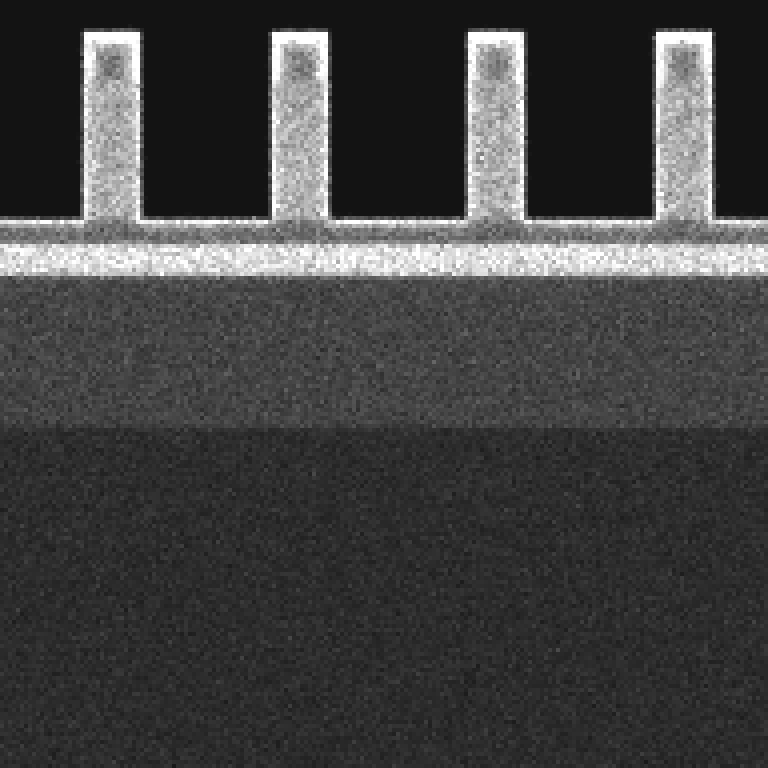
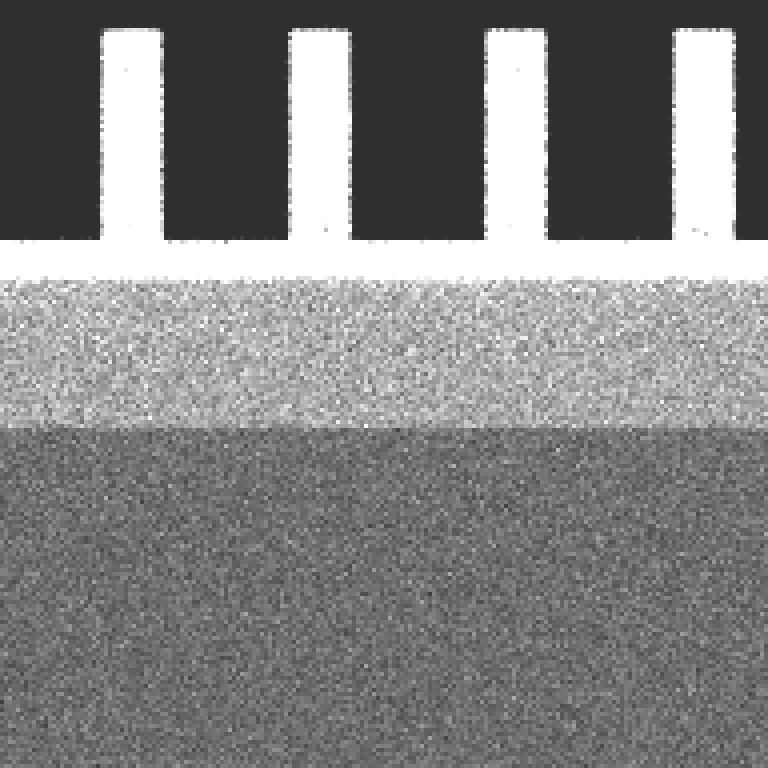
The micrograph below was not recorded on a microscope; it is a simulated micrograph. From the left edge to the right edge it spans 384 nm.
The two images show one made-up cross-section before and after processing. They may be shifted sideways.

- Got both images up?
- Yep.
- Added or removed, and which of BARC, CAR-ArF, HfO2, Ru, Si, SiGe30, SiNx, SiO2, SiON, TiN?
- removed, TiN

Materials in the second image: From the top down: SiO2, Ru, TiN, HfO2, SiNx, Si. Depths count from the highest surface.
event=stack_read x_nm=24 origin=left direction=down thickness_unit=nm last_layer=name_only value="empty 106, HfO2 16, SiNx 76, Si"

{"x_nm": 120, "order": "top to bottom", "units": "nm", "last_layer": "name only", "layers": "empty 106, HfO2 16, SiNx 76, Si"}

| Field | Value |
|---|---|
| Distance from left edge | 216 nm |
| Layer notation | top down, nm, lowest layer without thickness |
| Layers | empty 106, HfO2 16, SiNx 76, Si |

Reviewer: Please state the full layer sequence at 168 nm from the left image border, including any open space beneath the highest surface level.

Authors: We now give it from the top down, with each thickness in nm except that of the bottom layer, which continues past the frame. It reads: SiO2 24, Ru 70, TiN 12, HfO2 16, SiNx 76, Si